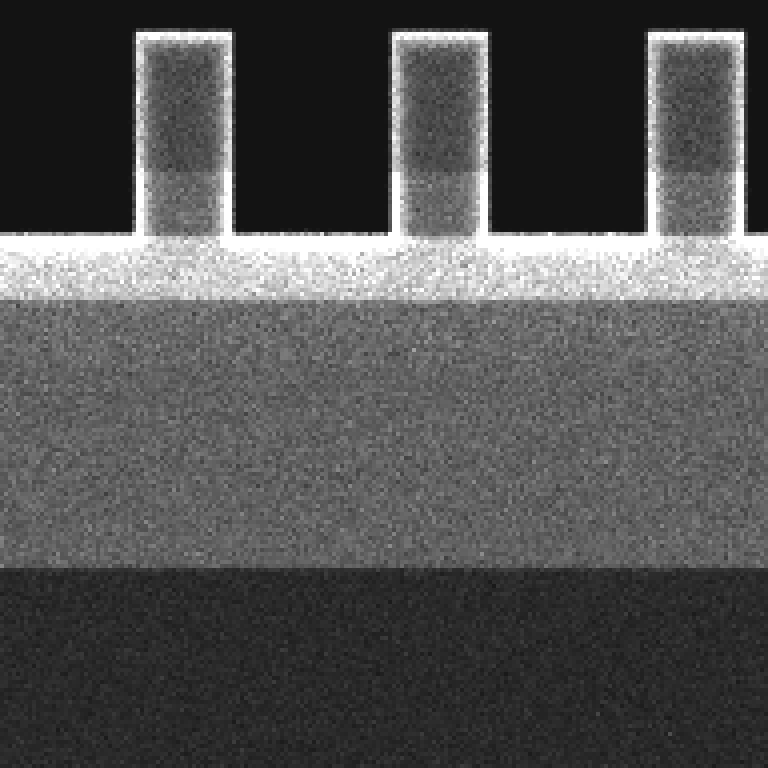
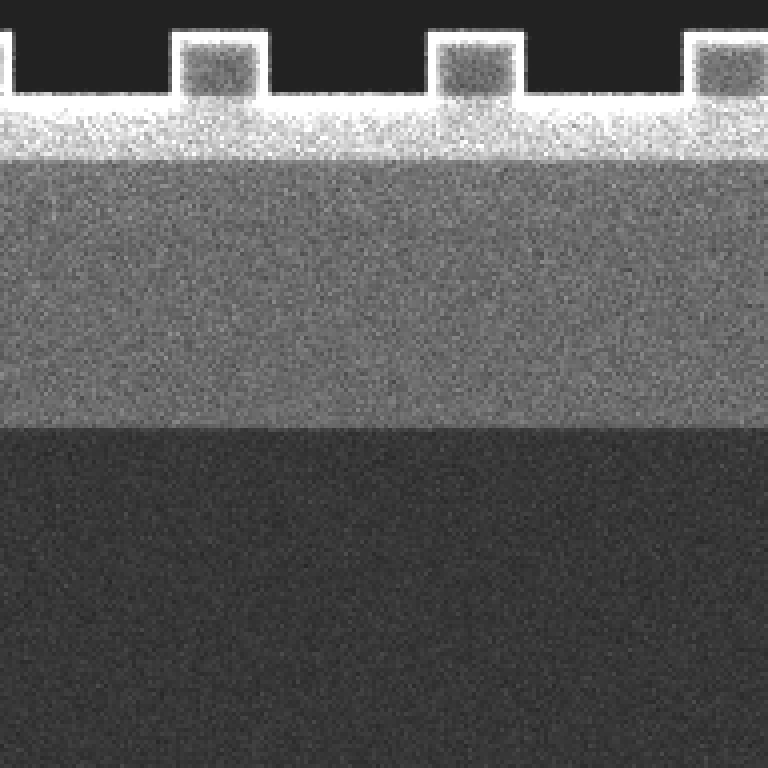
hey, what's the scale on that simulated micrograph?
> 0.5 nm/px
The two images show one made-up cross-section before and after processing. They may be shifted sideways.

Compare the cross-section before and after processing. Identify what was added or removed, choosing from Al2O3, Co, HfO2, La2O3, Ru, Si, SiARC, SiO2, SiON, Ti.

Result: SiARC removed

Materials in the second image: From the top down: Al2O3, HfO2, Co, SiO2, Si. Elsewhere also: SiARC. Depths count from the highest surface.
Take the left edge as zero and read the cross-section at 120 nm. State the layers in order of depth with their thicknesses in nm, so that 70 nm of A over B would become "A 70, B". Al2O3 32, HfO2 32, Co 32, SiO2 102, Si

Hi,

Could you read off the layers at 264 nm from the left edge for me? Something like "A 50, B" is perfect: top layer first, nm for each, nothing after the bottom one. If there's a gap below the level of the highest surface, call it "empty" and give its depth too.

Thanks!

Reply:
empty 32, HfO2 32, Co 32, SiO2 102, Si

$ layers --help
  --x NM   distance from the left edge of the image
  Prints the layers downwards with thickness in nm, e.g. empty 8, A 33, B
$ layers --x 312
empty 32, HfO2 32, Co 32, SiO2 102, Si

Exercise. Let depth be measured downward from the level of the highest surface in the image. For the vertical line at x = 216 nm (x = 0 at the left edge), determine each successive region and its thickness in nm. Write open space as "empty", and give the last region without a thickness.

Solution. Al2O3 32, HfO2 32, Co 32, SiO2 102, Si